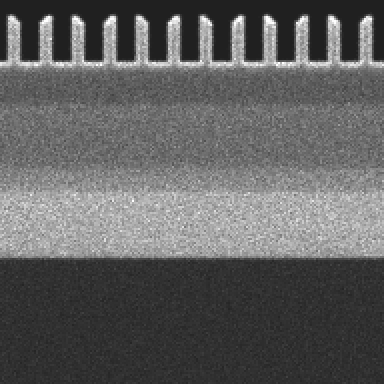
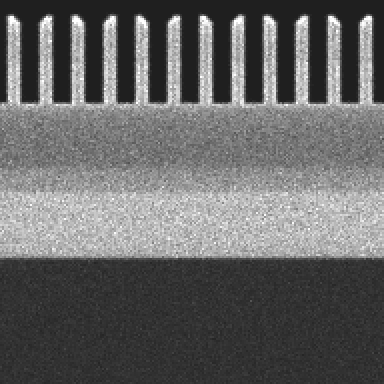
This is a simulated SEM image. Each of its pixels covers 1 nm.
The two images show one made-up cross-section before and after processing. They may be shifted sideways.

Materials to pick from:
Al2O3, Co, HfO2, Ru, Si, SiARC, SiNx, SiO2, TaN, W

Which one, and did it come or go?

Al2O3 - removed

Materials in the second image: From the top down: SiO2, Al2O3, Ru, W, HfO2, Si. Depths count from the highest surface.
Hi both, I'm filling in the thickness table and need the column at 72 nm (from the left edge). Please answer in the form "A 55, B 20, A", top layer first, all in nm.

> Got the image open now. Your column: SiO2 46, Al2O3 42, Ru 64, W 24, HfO2 66, Si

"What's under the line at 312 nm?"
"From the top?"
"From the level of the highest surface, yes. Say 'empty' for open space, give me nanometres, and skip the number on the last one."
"empty 88, Ru 64, W 24, HfO2 66, Si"